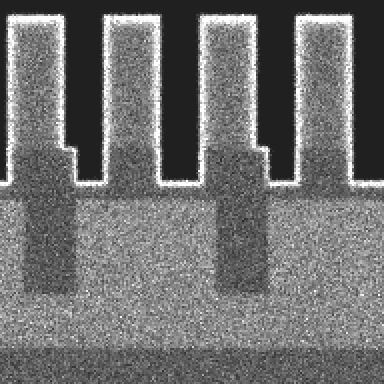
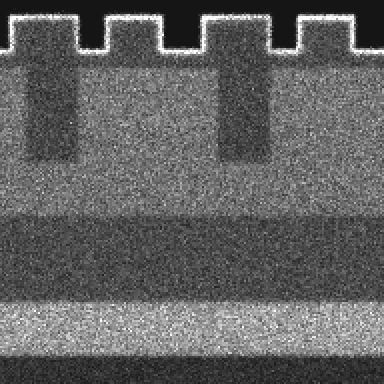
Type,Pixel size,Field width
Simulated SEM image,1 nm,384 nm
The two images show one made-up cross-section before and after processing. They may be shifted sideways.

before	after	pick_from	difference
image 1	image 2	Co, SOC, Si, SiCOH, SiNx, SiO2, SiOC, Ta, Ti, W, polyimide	SOC removed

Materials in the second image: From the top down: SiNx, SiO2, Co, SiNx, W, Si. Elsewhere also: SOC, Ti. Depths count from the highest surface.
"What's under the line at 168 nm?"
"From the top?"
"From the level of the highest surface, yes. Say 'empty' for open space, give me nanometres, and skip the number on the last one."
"empty 34, SiNx 18, SiO2 58, Co 90, SiNx 86, W 54, Si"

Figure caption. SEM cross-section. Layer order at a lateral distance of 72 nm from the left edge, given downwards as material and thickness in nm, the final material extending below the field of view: Ti 146, Co 54, SiNx 86, W 54, Si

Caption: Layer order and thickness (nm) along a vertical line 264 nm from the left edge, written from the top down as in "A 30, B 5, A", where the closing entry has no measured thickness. Ti 146, Co 54, SiNx 86, W 54, Si